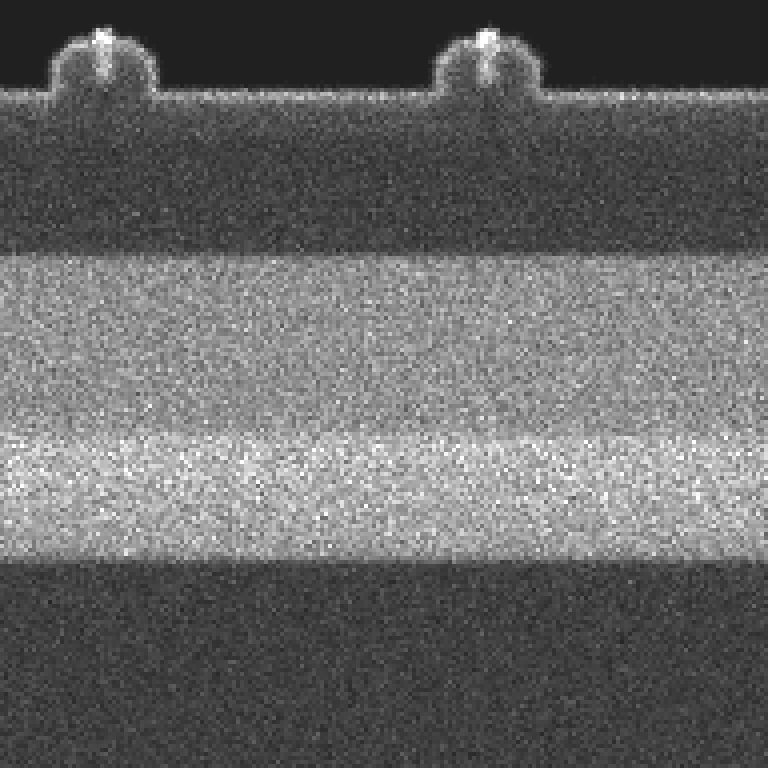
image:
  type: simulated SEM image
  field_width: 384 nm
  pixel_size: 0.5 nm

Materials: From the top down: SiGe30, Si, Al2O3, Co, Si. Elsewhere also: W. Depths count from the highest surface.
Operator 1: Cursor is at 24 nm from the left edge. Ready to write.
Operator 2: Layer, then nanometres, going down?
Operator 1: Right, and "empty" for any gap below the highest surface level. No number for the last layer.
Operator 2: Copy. empty 30, SiGe30 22, Si 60, Al2O3 90, Co 62, Si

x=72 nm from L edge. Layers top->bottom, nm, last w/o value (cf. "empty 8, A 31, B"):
empty 10, SiGe30 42, Si 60, Al2O3 90, Co 62, Si